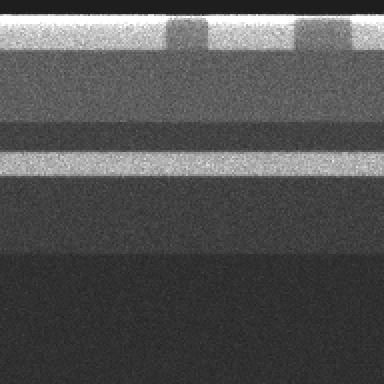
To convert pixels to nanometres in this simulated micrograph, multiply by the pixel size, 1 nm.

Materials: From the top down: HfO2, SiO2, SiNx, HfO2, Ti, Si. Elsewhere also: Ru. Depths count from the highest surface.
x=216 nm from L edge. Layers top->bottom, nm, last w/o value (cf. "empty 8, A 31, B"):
HfO2 34, SiO2 72, SiNx 30, HfO2 24, Ti 78, Si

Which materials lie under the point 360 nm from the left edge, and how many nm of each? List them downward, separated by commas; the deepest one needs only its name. HfO2 34, SiO2 72, SiNx 30, HfO2 24, Ti 78, Si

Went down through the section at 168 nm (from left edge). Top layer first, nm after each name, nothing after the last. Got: Ru 34, SiO2 72, SiNx 30, HfO2 24, Ti 78, Si